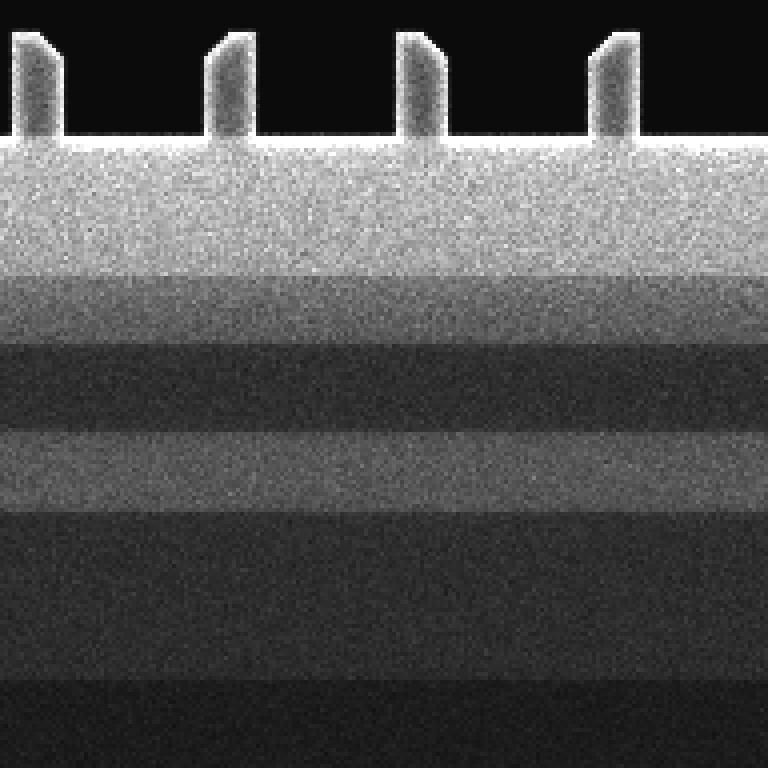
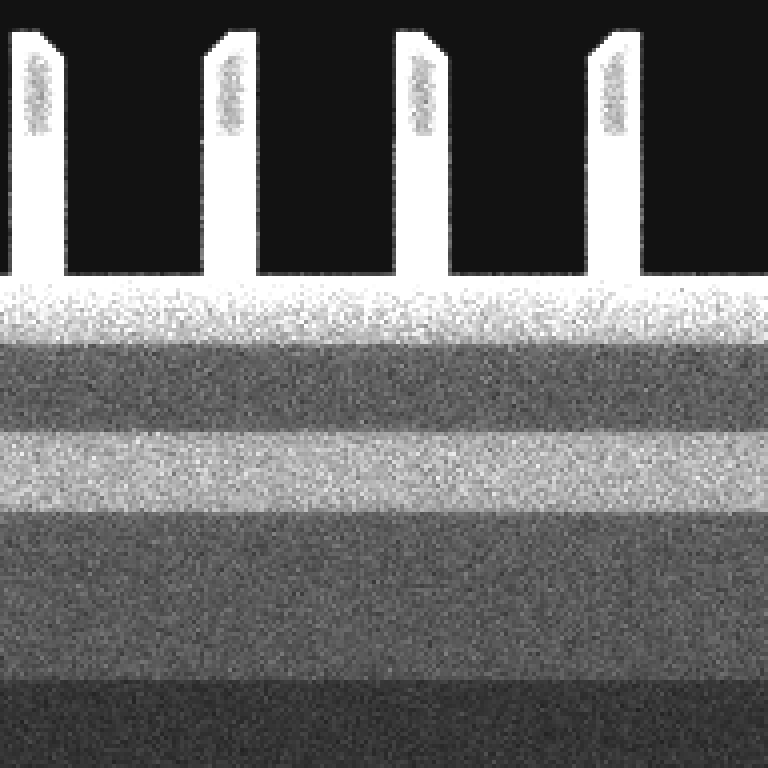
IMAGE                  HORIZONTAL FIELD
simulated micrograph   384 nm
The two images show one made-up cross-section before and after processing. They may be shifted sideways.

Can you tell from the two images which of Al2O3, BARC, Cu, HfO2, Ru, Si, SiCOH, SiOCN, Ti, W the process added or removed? Yes, it removed HfO2.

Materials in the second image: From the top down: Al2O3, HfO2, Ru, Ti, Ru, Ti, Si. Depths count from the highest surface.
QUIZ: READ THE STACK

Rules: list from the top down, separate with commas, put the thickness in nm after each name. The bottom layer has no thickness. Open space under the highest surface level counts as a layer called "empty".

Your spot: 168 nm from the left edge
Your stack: empty 122, Ru 34, Ti 44, Ru 40, Ti 84, Si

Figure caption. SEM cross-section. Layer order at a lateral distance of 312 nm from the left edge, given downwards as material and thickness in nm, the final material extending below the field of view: Al2O3 52, HfO2 70, Ru 34, Ti 44, Ru 40, Ti 84, Si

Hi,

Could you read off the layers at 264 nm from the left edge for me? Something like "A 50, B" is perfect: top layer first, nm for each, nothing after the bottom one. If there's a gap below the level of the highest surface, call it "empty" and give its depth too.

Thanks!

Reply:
empty 122, Ru 34, Ti 44, Ru 40, Ti 84, Si